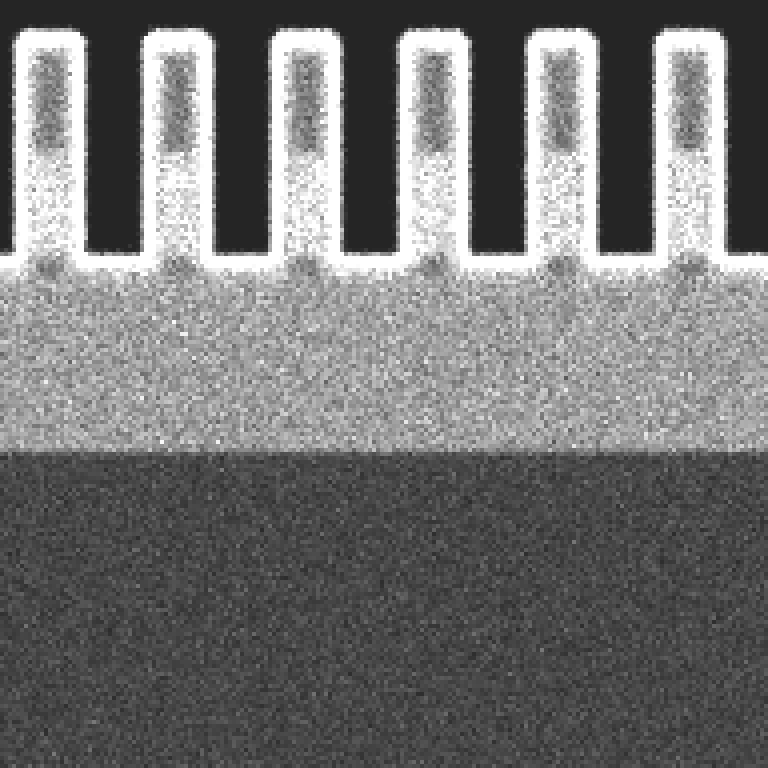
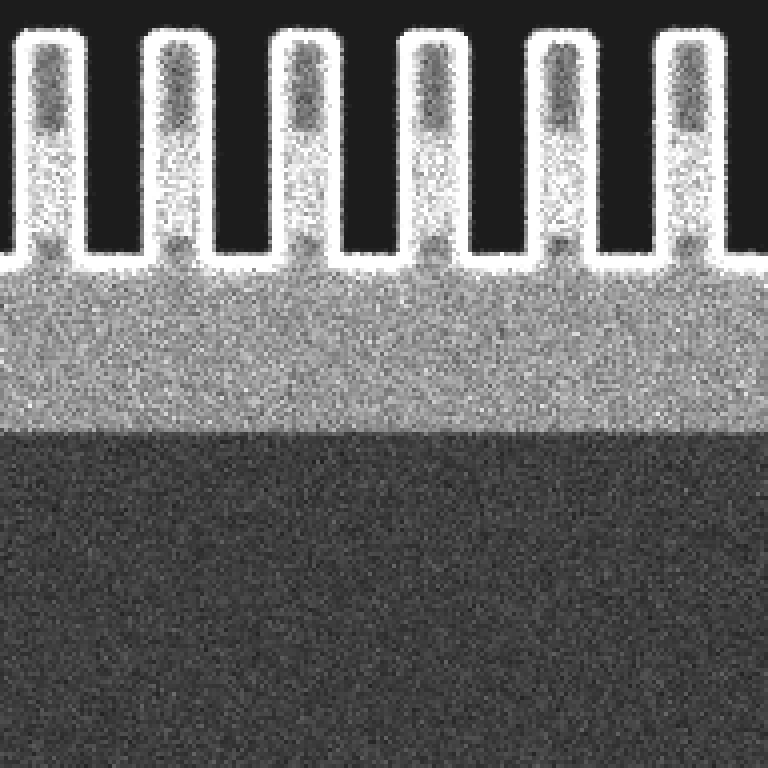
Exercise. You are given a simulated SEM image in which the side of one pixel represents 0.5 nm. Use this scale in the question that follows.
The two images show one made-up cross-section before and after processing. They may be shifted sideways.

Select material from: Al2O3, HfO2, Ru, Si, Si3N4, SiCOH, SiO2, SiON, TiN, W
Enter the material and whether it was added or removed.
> SiO2 / removed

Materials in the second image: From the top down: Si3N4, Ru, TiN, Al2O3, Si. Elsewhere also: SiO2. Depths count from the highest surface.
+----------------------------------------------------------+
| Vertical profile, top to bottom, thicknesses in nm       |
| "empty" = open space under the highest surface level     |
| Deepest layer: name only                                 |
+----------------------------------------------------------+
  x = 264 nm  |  empty 4, SiO2 108, Al2O3 88, Si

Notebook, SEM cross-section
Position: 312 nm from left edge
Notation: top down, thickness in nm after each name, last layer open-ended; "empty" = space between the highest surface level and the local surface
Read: empty 112, Al2O3 88, Si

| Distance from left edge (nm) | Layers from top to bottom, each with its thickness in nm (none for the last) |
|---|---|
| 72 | empty 4, SiO2 108, Al2O3 88, Si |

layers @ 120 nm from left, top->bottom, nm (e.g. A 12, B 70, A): empty 112, Al2O3 88, Si